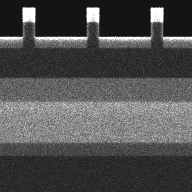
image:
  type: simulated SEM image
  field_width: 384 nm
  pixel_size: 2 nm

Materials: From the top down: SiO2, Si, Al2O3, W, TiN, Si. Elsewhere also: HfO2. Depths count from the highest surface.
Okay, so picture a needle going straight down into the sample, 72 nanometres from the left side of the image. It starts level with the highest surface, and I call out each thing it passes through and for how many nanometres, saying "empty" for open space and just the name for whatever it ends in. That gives empty 58, SiO2 22, Si 60, Al2O3 48, W 82, TiN 26, Si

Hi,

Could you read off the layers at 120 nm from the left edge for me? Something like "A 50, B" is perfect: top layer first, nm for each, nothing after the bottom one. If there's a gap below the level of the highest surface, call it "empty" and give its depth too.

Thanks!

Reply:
empty 58, SiO2 22, Si 60, Al2O3 48, W 82, TiN 26, Si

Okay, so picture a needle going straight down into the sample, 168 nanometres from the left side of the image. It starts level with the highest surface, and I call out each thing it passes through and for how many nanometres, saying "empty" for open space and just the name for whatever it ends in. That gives empty 58, SiO2 22, Si 60, Al2O3 48, W 82, TiN 26, Si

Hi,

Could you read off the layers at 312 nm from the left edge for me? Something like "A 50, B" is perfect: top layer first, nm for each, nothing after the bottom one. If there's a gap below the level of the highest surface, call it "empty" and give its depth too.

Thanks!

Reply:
HfO2 28, Si 112, Al2O3 48, W 82, TiN 26, Si